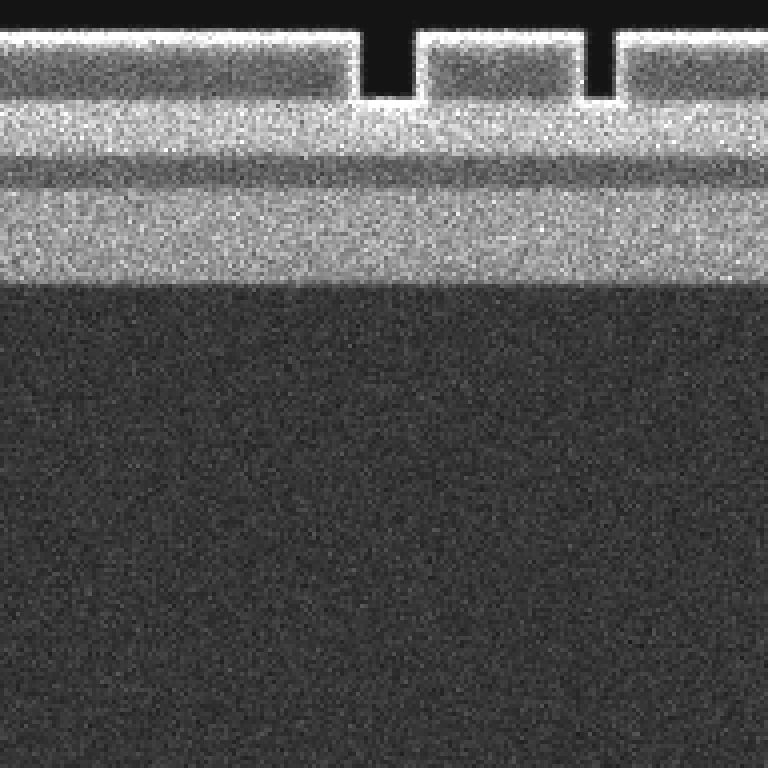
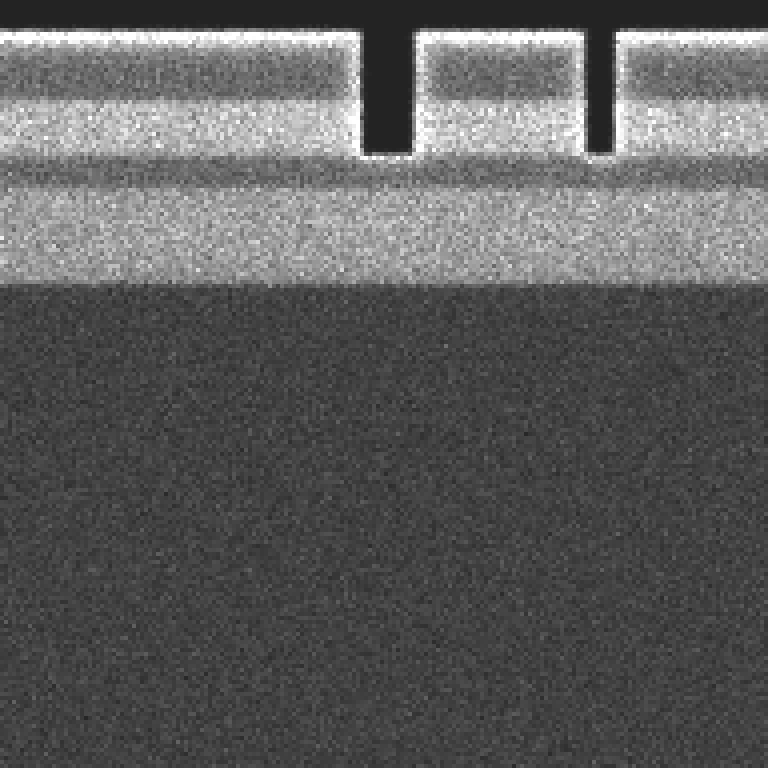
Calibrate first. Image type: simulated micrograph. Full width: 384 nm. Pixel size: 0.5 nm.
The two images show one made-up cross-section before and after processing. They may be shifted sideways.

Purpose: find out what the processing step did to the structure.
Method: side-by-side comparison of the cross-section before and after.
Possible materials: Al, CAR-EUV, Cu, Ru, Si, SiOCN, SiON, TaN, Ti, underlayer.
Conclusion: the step removed Ru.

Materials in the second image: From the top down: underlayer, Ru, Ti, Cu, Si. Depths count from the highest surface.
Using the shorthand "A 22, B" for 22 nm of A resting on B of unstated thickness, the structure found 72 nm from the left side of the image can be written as underlayer 34, Ru 28, Ti 16, Cu 48, Si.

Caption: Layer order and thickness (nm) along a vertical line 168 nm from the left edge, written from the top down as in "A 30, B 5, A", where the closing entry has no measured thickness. underlayer 34, Ru 28, Ti 16, Cu 48, Si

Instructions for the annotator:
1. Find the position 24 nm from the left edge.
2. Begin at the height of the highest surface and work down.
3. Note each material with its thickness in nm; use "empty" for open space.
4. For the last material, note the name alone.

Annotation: underlayer 34, Ru 28, Ti 16, Cu 48, Si